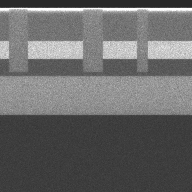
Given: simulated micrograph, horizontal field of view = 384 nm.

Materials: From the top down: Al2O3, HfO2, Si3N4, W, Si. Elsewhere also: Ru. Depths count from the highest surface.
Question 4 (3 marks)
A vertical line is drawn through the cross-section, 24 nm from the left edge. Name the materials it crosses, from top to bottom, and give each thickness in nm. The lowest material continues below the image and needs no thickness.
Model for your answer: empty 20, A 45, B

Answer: Ru 128, Si3N4 8, W 78, Si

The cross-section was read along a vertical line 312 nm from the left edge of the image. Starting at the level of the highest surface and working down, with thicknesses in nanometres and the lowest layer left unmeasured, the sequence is Al2O3 66, HfO2 36, Si3N4 34, W 78, Si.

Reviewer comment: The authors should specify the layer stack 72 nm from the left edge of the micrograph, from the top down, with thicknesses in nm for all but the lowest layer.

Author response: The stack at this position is Al2O3 66, HfO2 36, Si3N4 34, W 78, Si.